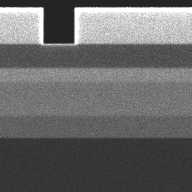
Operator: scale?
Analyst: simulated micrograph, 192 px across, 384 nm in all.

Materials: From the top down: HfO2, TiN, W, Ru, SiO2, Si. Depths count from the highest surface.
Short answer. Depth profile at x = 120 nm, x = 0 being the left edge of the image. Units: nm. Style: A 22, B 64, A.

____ empty 72, TiN 48, W 28, Ru 68, SiO2 44, Si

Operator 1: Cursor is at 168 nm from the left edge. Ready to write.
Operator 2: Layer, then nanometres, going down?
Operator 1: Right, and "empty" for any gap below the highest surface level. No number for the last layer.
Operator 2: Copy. HfO2 72, TiN 48, W 28, Ru 68, SiO2 44, Si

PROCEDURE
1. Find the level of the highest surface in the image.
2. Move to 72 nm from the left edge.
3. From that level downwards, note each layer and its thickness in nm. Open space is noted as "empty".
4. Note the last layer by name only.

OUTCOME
HfO2 72, TiN 48, W 28, Ru 68, SiO2 44, Si